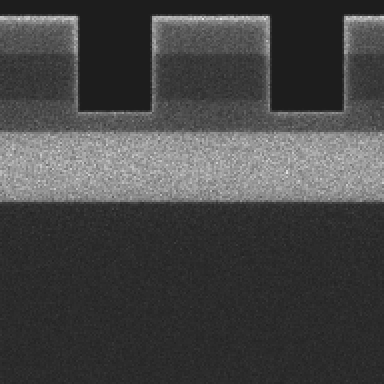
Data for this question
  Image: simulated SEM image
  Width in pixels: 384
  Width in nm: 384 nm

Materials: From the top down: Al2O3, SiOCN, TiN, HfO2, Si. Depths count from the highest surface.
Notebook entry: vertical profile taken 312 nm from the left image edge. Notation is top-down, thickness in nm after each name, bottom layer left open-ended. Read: empty 96, TiN 20, HfO2 70, Si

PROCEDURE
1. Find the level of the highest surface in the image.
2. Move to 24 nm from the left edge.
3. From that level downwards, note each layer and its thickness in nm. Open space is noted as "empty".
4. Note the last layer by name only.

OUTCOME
Al2O3 38, SiOCN 46, TiN 32, HfO2 70, Si